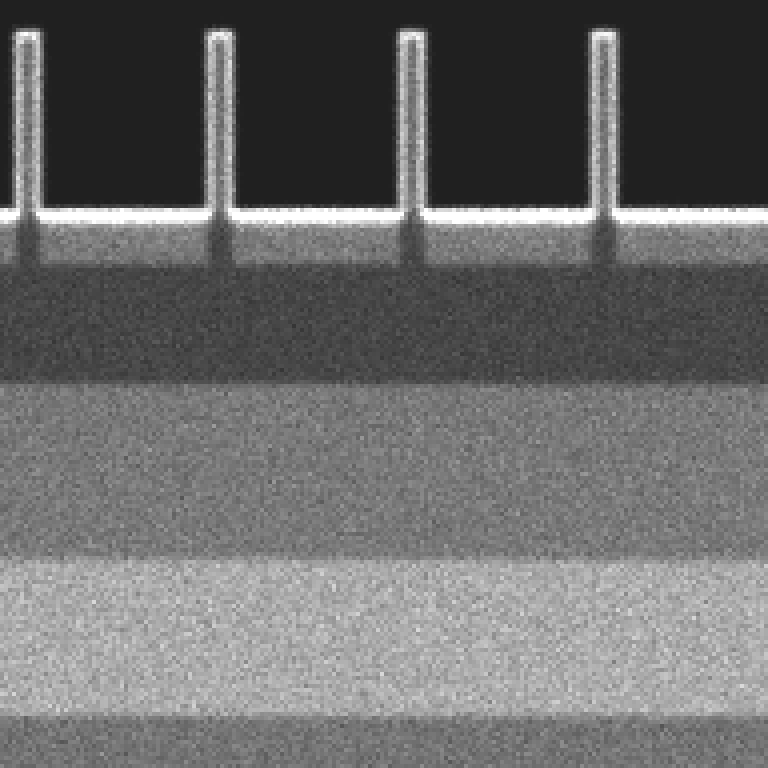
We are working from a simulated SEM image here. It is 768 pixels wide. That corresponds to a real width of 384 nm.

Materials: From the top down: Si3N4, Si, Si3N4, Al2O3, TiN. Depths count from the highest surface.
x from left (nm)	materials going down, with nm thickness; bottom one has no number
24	empty 90, Si3N4 26, Si 60, Si3N4 88, Al2O3 78, TiN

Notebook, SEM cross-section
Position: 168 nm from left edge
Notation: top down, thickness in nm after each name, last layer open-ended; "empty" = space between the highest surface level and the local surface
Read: empty 90, Si3N4 26, Si 60, Si3N4 88, Al2O3 78, TiN